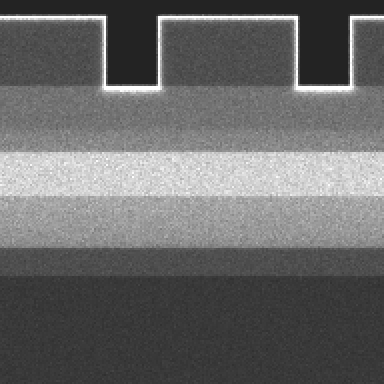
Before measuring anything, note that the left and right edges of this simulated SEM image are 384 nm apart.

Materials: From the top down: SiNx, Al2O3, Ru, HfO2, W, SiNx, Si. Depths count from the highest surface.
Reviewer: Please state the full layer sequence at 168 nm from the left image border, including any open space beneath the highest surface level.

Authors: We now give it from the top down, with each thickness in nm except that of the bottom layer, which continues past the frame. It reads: SiNx 70, Al2O3 44, Ru 22, HfO2 44, W 52, SiNx 28, Si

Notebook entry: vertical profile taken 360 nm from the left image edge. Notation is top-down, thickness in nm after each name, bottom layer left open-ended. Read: SiNx 70, Al2O3 44, Ru 22, HfO2 44, W 52, SiNx 28, Si